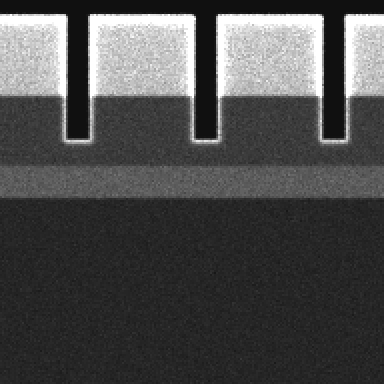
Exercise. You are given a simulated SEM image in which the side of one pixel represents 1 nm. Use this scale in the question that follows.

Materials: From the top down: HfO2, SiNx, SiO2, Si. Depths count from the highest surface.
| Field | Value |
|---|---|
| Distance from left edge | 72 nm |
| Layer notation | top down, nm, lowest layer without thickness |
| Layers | empty 124, SiNx 26, SiO2 32, Si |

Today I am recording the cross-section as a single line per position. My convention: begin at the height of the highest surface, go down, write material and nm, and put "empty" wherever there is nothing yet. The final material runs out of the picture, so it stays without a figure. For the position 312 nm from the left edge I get HfO2 80, SiNx 70, SiO2 32, Si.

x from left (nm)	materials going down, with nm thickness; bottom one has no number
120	HfO2 80, SiNx 70, SiO2 32, Si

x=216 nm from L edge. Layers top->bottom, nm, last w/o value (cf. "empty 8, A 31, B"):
empty 124, SiNx 26, SiO2 32, Si